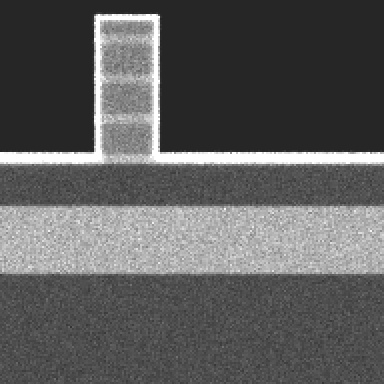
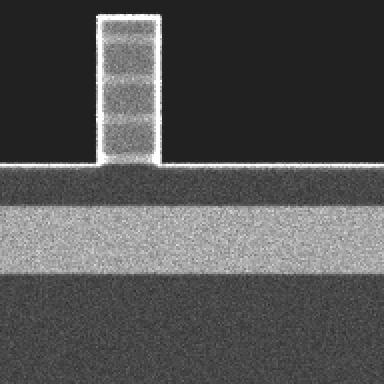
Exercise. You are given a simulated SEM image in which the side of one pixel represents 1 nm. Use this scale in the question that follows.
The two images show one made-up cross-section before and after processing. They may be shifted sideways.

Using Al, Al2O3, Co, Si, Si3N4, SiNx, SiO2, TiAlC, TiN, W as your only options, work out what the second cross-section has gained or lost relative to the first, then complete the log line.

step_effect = removed Al2O3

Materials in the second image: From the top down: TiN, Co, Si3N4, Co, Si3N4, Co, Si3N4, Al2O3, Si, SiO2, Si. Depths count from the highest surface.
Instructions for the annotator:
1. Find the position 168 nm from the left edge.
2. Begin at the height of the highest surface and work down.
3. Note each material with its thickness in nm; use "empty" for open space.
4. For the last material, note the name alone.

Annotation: empty 148, Si 42, SiO2 68, Si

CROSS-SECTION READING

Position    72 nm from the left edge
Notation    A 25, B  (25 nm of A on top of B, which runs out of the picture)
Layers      empty 148, Si 42, SiO2 68, Si